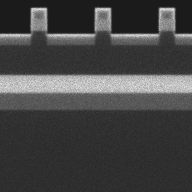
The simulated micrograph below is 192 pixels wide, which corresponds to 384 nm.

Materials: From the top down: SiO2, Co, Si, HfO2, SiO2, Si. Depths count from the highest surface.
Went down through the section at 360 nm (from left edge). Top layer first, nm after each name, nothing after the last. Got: empty 52, SiO2 22, Si 60, HfO2 36, SiO2 34, Si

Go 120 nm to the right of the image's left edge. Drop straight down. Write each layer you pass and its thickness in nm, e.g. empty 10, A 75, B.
empty 52, SiO2 22, Si 60, HfO2 36, SiO2 34, Si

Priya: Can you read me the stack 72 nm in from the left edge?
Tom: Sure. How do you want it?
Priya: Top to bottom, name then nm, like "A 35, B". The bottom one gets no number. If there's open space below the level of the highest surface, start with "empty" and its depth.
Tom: SiO2 22, Co 24, Si 88, HfO2 36, SiO2 34, Si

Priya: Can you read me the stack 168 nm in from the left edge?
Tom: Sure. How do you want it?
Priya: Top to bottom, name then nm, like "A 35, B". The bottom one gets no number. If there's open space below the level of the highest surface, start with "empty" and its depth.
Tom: empty 52, SiO2 22, Si 60, HfO2 36, SiO2 34, Si